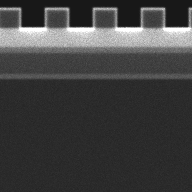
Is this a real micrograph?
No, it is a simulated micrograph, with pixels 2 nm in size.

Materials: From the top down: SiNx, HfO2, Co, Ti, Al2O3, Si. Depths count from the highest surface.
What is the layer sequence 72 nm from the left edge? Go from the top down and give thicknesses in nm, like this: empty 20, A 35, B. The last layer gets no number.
empty 40, HfO2 38, Co 12, Ti 42, Al2O3 10, Si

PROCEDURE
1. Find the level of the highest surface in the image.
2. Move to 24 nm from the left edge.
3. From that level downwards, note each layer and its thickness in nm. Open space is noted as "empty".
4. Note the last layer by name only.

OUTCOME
SiNx 40, HfO2 38, Co 12, Ti 42, Al2O3 10, Si